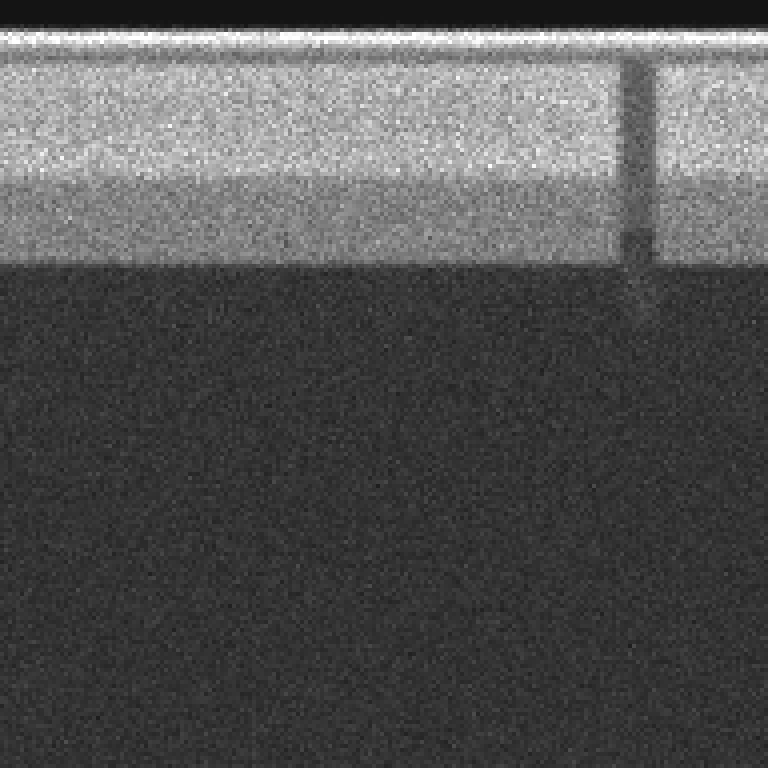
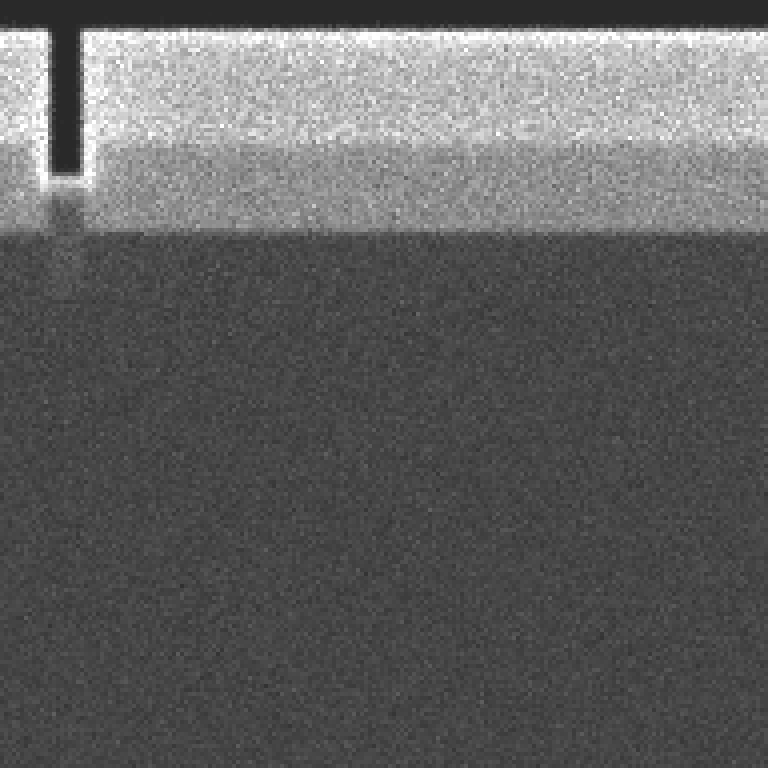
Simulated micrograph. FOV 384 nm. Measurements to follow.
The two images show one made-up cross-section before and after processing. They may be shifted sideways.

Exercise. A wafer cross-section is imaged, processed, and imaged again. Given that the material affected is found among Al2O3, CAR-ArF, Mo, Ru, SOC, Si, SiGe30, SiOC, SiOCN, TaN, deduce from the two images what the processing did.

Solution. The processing removed SOC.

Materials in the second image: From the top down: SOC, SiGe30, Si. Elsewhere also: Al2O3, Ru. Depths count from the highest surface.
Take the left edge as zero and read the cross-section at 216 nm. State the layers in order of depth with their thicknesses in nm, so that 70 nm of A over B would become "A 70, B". Ru 56, Al2O3 44, Si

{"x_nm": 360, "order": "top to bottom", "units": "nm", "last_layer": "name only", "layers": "Ru 56, Al2O3 44, Si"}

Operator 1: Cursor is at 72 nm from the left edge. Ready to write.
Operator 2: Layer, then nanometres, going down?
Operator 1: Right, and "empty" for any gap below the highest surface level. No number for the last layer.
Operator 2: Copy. Ru 56, Al2O3 44, Si